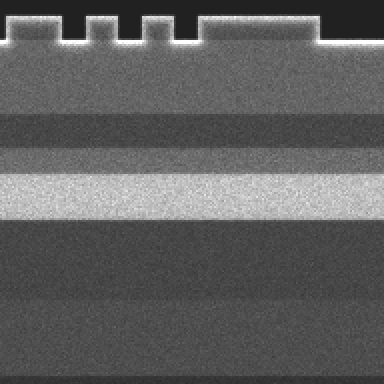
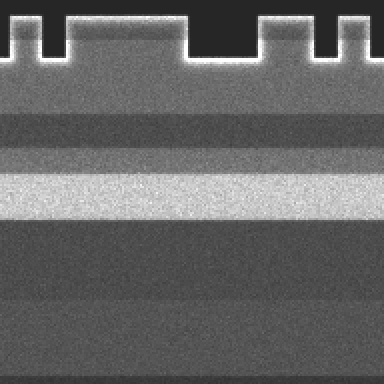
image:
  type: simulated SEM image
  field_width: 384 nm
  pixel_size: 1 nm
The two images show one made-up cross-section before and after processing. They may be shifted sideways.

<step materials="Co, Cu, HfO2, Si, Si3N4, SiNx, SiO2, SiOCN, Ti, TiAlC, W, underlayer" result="removed SiO2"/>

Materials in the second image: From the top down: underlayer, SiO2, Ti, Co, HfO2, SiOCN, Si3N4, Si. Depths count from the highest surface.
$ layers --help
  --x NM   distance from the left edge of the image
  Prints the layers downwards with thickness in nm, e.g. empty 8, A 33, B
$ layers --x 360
underlayer 24, SiO2 74, Ti 34, Co 26, HfO2 46, SiOCN 80, Si3N4 76, Si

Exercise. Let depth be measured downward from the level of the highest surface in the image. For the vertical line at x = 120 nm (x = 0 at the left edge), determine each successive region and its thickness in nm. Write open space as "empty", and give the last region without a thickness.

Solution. underlayer 24, SiO2 74, Ti 34, Co 26, HfO2 46, SiOCN 80, Si3N4 76, Si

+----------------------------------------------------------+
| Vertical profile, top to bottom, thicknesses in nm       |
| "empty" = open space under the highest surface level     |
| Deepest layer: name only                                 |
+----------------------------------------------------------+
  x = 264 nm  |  underlayer 24, SiO2 74, Ti 34, Co 26, HfO2 46, SiOCN 80, Si3N4 76, Si